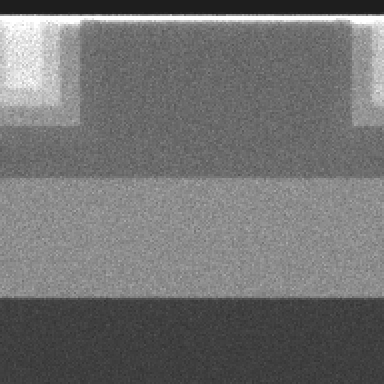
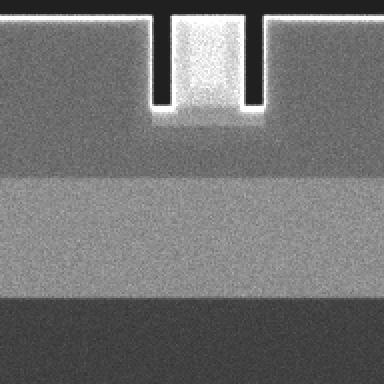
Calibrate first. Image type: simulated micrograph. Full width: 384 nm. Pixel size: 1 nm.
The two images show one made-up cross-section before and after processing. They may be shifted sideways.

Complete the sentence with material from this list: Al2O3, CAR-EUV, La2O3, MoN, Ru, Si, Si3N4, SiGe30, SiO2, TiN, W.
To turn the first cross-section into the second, Al2O3 must be removed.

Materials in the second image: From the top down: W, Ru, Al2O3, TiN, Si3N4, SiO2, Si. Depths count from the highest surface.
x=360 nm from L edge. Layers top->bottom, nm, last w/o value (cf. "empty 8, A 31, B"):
Si3N4 162, SiO2 120, Si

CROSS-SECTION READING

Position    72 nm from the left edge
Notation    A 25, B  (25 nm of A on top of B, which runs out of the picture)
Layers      Si3N4 162, SiO2 120, Si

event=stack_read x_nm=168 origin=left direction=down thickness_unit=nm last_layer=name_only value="empty 90, Al2O3 20, TiN 18, Si3N4 34, SiO2 120, Si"